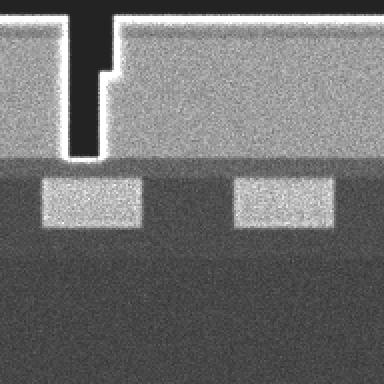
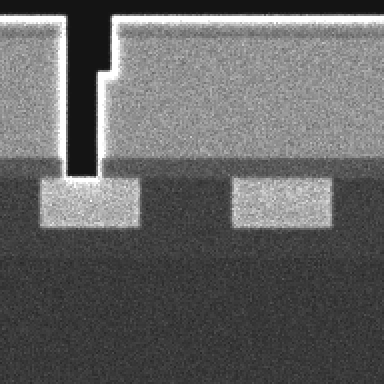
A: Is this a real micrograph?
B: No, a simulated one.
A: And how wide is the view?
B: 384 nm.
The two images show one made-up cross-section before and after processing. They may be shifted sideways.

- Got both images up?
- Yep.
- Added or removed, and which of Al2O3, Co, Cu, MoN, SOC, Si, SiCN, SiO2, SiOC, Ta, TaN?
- removed, SiCN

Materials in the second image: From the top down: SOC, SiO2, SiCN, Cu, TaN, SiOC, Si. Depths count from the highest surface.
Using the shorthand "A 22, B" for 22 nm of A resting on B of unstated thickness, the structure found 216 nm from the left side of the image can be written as SOC 22, SiO2 120, SiCN 20, SiOC 80, Si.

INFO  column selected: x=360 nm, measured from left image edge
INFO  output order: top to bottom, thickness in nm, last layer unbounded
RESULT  SOC 22, SiO2 120, SiCN 20, SiOC 80, Si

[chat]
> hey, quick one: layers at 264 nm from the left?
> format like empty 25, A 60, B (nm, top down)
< SOC 22, SiO2 120, SiCN 20, Cu 44, TaN 6, SiOC 30, Si